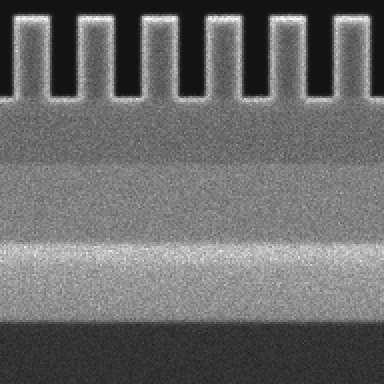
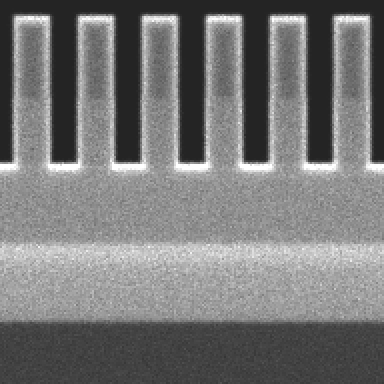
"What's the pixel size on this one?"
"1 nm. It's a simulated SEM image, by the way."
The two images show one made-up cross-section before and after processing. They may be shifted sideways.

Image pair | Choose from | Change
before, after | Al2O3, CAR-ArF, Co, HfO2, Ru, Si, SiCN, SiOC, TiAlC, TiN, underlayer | TiN (removed)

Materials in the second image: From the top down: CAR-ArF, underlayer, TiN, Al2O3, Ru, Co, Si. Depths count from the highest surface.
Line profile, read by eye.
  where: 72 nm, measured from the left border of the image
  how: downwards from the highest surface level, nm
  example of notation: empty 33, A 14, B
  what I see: empty 148, Al2O3 80, Ru 20, Co 58, Si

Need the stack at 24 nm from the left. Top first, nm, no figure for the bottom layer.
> CAR-ArF 44, underlayer 38, TiN 66, Al2O3 80, Ru 20, Co 58, Si